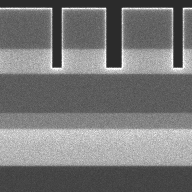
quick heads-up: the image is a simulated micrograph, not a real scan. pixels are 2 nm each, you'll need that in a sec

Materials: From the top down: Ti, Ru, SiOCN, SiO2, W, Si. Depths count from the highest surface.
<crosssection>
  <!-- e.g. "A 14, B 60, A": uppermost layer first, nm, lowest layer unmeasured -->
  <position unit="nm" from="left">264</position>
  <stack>Ti 82, Ru 50, SiOCN 78, SiO2 32, W 74, Si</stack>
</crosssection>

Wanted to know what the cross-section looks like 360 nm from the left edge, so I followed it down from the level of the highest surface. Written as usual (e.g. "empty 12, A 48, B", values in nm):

empty 120, Ru 12, SiOCN 78, SiO2 32, W 74, Si